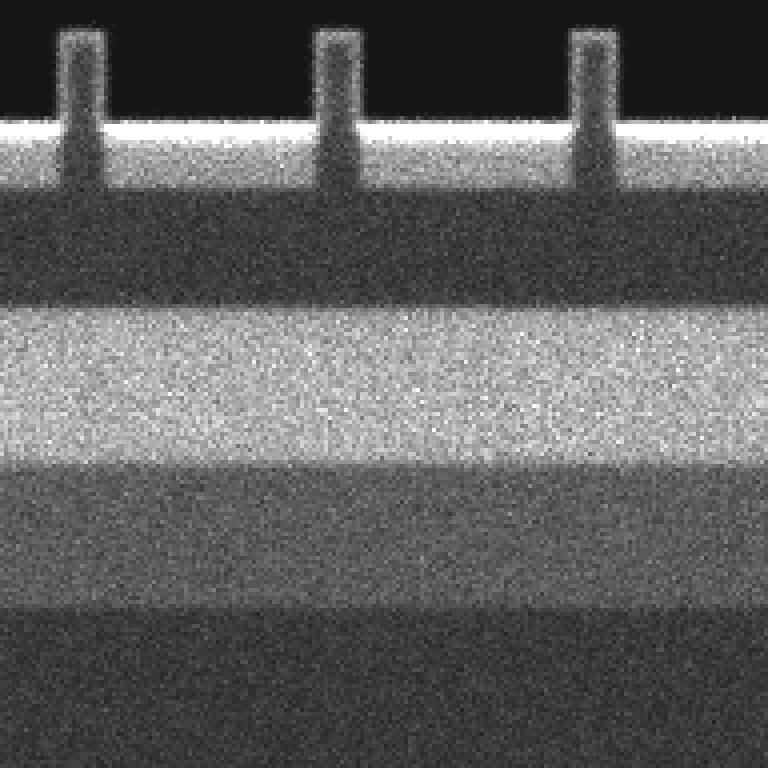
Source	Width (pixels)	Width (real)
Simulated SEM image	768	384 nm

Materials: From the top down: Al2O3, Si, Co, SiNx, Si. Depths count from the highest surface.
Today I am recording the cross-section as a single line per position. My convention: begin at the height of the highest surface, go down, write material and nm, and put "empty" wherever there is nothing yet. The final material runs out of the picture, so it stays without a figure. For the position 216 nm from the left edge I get empty 46, Al2O3 32, Si 60, Co 78, SiNx 72, Si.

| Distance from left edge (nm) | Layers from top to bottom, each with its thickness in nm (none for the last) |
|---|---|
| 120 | empty 46, Al2O3 32, Si 60, Co 78, SiNx 72, Si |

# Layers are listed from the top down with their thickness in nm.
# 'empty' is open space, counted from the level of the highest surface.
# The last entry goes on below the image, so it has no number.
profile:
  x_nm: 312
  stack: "empty 46, Al2O3 32, Si 60, Co 78, SiNx 72, Si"